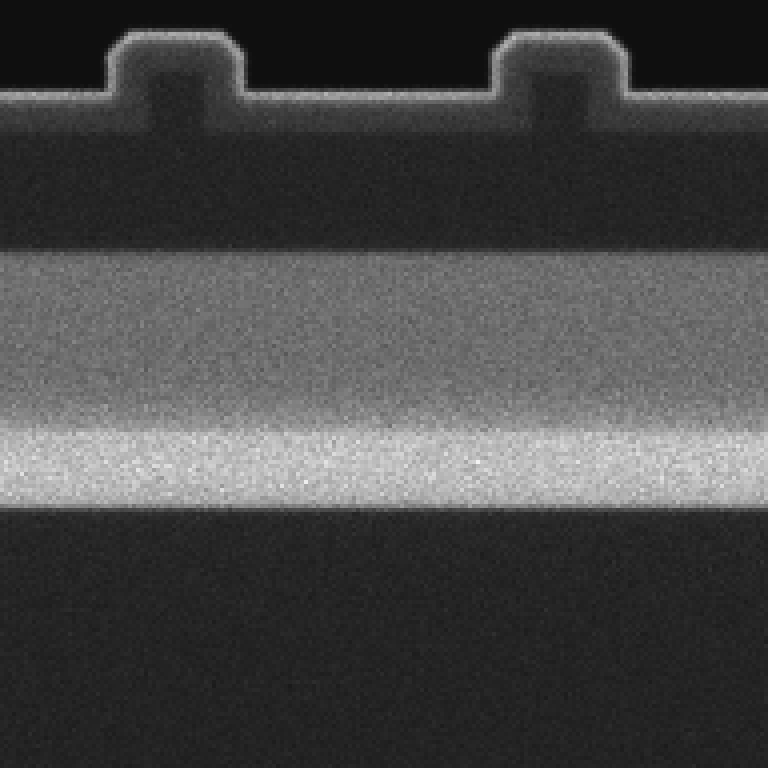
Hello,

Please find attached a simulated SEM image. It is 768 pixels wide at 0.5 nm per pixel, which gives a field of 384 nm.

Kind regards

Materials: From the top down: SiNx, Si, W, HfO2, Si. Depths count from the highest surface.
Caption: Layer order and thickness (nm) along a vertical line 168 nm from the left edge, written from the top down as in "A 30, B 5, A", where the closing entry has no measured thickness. empty 30, SiNx 20, Si 60, W 90, HfO2 38, Si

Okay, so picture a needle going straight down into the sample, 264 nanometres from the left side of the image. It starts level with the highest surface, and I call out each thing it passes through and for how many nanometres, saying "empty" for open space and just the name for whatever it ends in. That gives SiNx 50, Si 60, W 90, HfO2 38, Si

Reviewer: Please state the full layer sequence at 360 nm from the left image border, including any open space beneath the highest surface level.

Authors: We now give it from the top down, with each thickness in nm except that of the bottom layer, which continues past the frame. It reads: empty 30, SiNx 20, Si 60, W 90, HfO2 38, Si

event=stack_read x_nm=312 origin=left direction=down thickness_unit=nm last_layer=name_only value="empty 10, SiNx 40, Si 60, W 90, HfO2 38, Si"